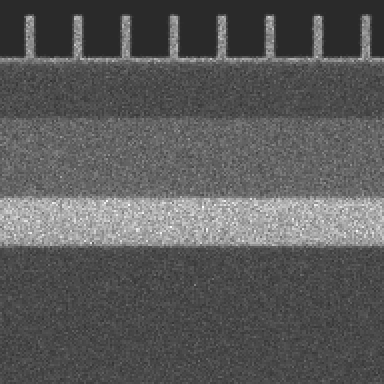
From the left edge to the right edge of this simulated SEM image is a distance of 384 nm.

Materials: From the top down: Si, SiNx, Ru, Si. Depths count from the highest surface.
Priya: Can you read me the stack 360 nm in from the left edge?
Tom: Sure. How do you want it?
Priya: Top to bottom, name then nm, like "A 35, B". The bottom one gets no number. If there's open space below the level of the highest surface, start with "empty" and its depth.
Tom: empty 42, Si 60, SiNx 80, Ru 48, Si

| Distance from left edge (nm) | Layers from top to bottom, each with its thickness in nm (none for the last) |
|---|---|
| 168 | empty 42, Si 60, SiNx 80, Ru 48, Si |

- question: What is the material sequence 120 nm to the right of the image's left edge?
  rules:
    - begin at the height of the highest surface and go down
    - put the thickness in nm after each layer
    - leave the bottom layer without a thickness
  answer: empty 42, Si 60, SiNx 80, Ru 48, Si